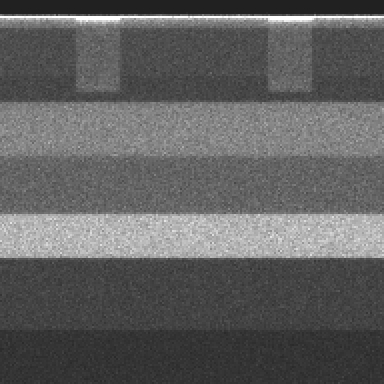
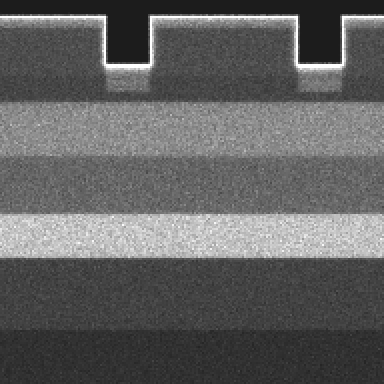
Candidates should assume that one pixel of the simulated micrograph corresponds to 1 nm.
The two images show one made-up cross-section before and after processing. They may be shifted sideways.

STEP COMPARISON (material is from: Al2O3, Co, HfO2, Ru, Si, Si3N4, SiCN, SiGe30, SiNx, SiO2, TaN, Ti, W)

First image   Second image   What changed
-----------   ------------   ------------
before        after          SiO2, removed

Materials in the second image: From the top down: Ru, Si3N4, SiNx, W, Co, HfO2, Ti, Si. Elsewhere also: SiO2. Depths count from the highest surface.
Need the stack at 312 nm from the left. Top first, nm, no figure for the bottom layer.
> empty 48, SiO2 16, Ru 12, SiNx 10, W 54, Co 58, HfO2 44, Ti 72, Si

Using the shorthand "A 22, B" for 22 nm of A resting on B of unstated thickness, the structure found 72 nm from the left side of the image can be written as Ru 12, Si3N4 48, SiNx 26, W 54, Co 58, HfO2 44, Ti 72, Si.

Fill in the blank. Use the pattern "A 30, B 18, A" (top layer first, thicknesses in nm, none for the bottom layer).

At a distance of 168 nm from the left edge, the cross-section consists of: Ru 12, Si3N4 48, SiNx 26, W 54, Co 58, HfO2 44, Ti 72, Si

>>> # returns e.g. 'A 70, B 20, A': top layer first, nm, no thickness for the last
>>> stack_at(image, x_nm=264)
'Ru 12, Si3N4 48, SiNx 26, W 54, Co 58, HfO2 44, Ti 72, Si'